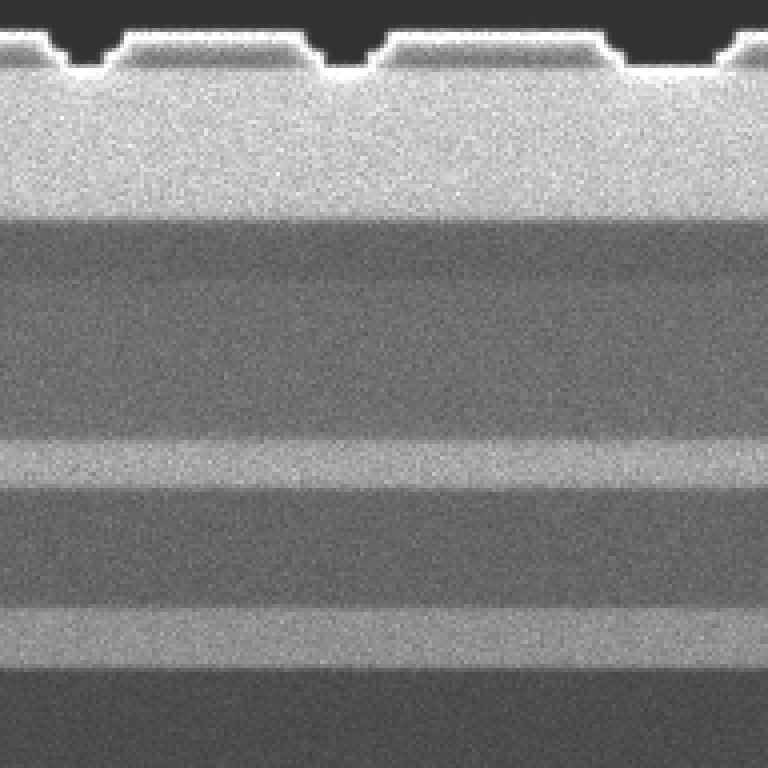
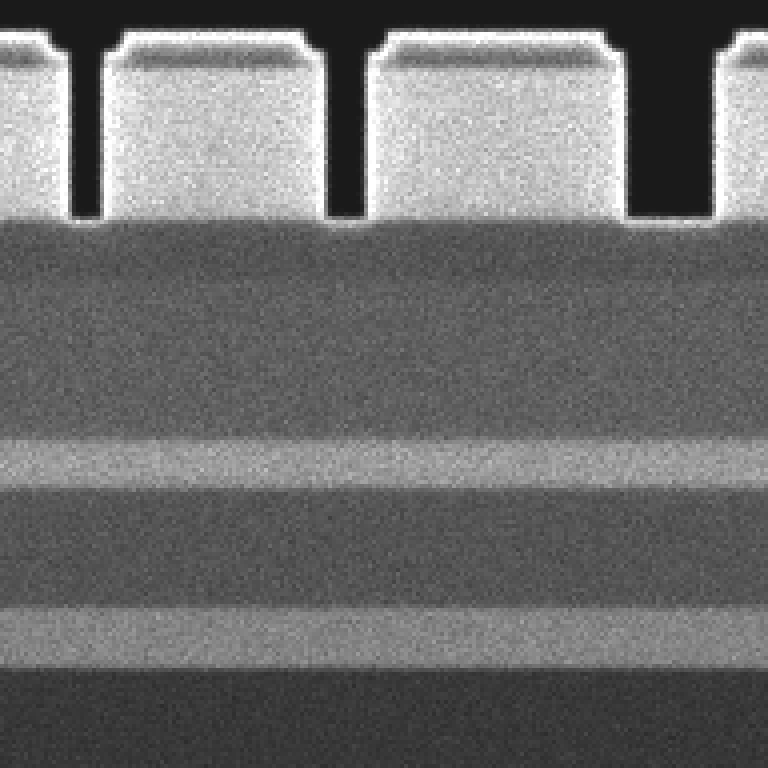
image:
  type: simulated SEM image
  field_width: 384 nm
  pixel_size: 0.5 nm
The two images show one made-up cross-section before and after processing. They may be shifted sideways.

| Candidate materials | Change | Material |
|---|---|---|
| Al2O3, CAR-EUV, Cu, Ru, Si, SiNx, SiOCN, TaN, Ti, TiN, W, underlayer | removed | W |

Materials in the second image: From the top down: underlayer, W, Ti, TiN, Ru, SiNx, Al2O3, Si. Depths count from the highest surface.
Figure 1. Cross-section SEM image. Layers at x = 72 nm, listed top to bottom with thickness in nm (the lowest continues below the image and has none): underlayer 18, W 76, Ti 30, TiN 80, Ru 24, SiNx 60, Al2O3 30, Si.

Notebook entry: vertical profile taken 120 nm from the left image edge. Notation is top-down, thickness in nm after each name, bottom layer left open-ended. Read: underlayer 18, W 76, Ti 30, TiN 80, Ru 24, SiNx 60, Al2O3 30, Si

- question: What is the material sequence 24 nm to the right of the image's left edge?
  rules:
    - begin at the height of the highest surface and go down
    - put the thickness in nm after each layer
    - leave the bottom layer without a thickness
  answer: empty 6, underlayer 12, W 76, Ti 30, TiN 80, Ru 24, SiNx 60, Al2O3 30, Si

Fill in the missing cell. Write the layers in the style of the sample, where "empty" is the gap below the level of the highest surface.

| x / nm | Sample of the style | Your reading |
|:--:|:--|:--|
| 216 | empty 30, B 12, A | underlayer 18, W 76, Ti 30, TiN 80, Ru 24, SiNx 60, Al2O3 30, Si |